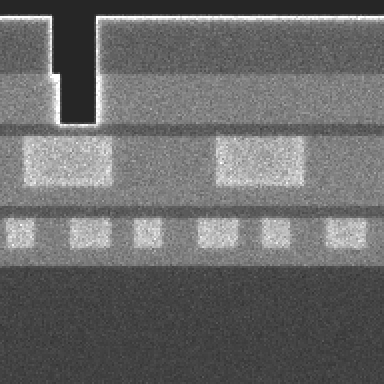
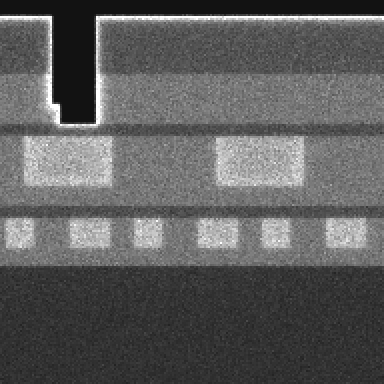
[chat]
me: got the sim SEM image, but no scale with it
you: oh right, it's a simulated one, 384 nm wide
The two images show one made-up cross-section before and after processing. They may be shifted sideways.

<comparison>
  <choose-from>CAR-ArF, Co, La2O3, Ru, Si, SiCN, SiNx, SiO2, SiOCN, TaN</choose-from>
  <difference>SiO2 removed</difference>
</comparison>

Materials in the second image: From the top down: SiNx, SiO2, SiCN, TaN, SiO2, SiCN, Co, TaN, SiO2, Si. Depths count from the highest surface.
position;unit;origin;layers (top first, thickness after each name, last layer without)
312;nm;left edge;SiNx 58, SiO2 50, SiCN 12, SiO2 70, SiCN 12, SiO2 48, Si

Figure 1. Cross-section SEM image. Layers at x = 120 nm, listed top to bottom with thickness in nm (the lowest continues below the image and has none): SiNx 58, SiO2 50, SiCN 12, SiO2 70, SiCN 12, SiO2 48, Si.